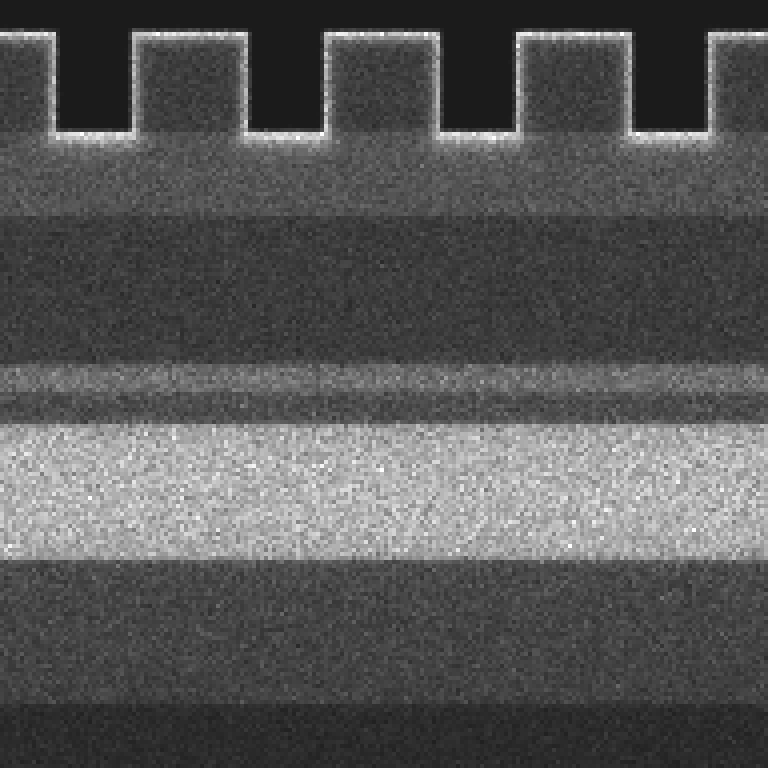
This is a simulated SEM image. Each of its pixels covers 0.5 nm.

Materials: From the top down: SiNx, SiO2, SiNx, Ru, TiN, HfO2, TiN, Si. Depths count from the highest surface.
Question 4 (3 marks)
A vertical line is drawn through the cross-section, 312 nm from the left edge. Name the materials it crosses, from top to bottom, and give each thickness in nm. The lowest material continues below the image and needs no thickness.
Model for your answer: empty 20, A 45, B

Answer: SiNx 50, SiO2 42, SiNx 74, Ru 14, TiN 16, HfO2 68, TiN 72, Si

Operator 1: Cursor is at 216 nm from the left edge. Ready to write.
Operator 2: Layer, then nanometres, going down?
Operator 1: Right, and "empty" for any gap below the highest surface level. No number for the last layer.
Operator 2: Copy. SiNx 50, SiO2 42, SiNx 74, Ru 14, TiN 16, HfO2 68, TiN 72, Si